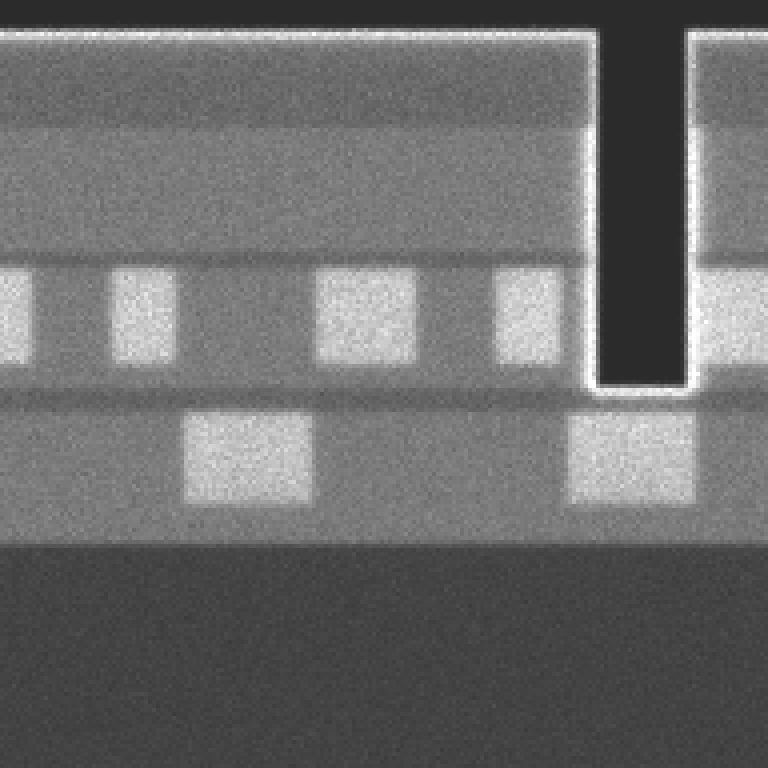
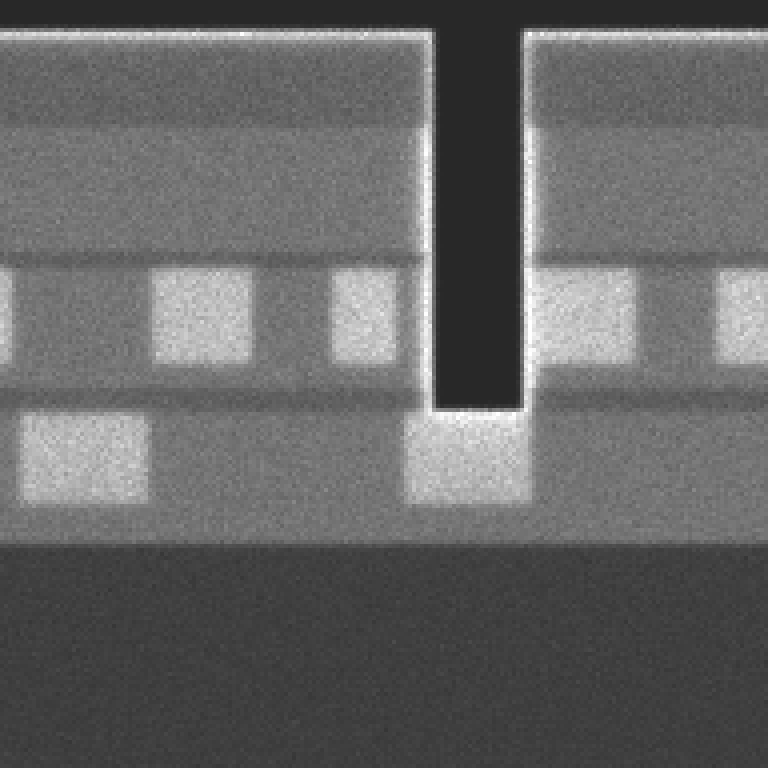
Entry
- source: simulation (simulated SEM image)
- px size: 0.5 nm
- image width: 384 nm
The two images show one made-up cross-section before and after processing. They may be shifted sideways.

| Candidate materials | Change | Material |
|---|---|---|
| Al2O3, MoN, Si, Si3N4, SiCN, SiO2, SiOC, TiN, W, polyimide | removed | Si3N4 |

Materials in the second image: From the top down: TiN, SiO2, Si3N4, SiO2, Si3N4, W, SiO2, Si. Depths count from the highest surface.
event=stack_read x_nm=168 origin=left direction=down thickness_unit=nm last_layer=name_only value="TiN 48, SiO2 62, Si3N4 8, W 48, SiO2 12, Si3N4 12, SiO2 66, Si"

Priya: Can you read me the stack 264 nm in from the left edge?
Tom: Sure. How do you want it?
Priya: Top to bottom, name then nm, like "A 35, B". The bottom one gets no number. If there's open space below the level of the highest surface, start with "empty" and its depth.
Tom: TiN 48, SiO2 62, Si3N4 8, SiO2 60, Si3N4 12, W 46, SiO2 20, Si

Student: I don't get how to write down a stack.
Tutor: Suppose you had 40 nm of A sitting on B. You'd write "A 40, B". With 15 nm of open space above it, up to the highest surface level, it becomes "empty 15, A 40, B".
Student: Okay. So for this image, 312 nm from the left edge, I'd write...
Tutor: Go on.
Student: TiN 48, SiO2 62, Si3N4 8, W 48, SiO2 12, Si3N4 12, SiO2 66, Si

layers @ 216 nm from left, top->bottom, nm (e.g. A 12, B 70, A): empty 190, W 46, SiO2 20, Si